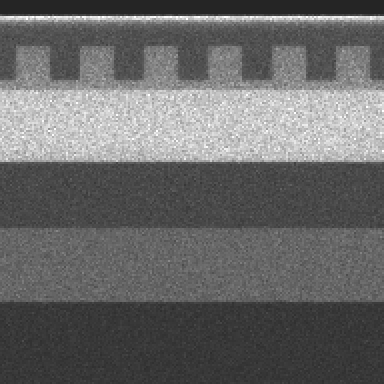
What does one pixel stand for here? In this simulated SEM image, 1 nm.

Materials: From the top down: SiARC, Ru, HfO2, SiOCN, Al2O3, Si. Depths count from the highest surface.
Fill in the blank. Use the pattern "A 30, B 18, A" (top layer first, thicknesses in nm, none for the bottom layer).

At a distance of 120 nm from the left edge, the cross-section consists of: SiARC 64, Ru 10, HfO2 72, SiOCN 66, Al2O3 74, Si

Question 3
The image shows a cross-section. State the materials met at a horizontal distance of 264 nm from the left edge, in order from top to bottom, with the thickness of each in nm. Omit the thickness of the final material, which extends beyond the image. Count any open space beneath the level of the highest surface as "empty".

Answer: SiARC 64, Ru 10, HfO2 72, SiOCN 66, Al2O3 74, Si